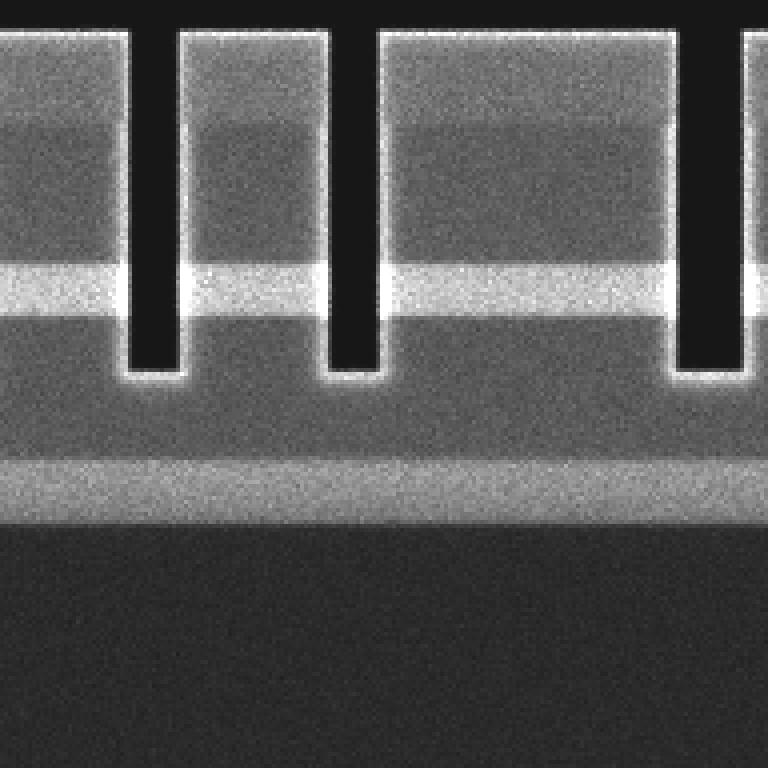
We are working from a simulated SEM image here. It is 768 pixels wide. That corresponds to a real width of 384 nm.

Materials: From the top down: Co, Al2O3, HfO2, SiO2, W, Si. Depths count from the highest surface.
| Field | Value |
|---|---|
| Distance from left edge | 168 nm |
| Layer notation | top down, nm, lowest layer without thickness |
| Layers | empty 170, SiO2 44, W 32, Si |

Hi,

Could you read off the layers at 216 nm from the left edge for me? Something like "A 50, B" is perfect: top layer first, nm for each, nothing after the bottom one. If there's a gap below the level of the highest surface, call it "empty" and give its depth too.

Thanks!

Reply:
Co 46, Al2O3 70, HfO2 26, SiO2 72, W 32, Si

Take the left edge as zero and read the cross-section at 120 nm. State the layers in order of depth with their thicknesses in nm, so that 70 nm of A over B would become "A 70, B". Co 46, Al2O3 70, HfO2 26, SiO2 72, W 32, Si